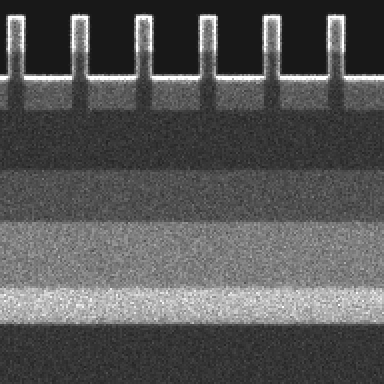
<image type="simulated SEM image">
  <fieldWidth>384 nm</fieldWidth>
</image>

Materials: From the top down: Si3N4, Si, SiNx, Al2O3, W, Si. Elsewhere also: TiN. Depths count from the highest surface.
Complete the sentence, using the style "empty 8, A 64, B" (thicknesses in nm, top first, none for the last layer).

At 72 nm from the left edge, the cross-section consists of TiN 36, Si 118, SiNx 52, Al2O3 66, W 36, Si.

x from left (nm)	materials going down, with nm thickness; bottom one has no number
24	empty 60, Si3N4 34, Si 60, SiNx 52, Al2O3 66, W 36, Si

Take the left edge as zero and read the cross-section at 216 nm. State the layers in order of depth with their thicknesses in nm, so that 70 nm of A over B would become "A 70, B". empty 60, Si3N4 34, Si 60, SiNx 52, Al2O3 66, W 36, Si